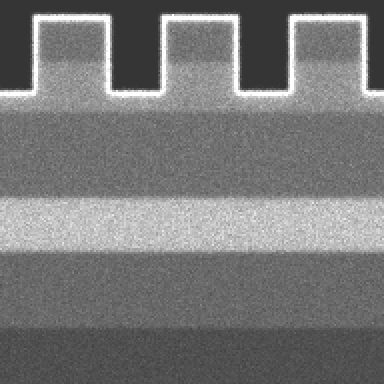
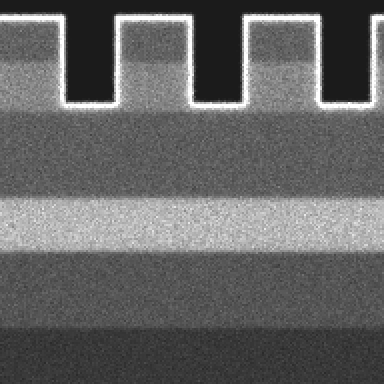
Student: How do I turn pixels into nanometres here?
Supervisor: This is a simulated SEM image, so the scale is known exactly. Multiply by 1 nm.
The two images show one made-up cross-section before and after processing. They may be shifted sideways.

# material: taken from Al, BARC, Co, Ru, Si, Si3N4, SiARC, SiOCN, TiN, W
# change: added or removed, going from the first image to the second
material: Co
change: removed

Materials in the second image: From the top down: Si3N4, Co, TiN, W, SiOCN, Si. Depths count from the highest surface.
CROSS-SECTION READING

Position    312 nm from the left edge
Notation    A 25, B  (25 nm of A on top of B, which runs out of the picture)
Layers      Si3N4 46, Co 50, TiN 86, W 54, SiOCN 76, Si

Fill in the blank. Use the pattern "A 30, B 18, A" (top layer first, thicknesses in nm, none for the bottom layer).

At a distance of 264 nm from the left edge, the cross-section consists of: Si3N4 46, Co 50, TiN 86, W 54, SiOCN 76, Si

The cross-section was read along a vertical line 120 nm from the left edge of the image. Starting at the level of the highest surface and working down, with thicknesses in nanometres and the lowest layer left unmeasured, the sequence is Si3N4 46, Co 50, TiN 86, W 54, SiOCN 76, Si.